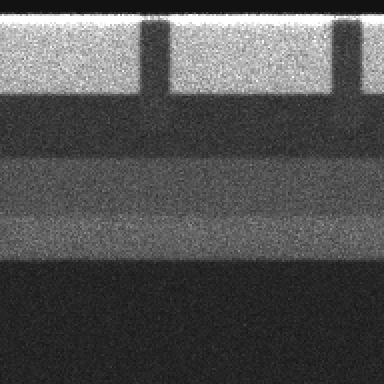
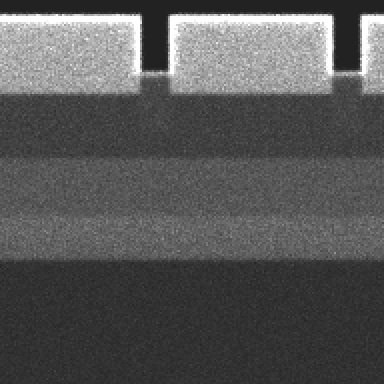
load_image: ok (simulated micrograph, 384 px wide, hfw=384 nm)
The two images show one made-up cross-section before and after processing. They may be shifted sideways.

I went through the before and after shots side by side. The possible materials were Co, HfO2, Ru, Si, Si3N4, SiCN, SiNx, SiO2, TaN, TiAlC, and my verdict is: removed, Si3N4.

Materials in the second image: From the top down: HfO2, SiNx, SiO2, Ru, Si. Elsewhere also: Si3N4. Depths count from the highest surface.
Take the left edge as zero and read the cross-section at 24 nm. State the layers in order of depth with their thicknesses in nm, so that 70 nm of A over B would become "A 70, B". HfO2 78, SiNx 64, SiO2 58, Ru 44, Si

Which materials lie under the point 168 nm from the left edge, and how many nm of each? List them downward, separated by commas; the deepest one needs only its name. empty 56, Si3N4 58, SiNx 28, SiO2 58, Ru 44, Si